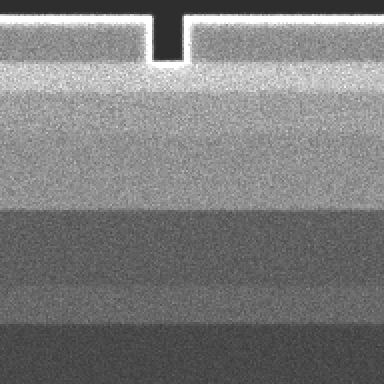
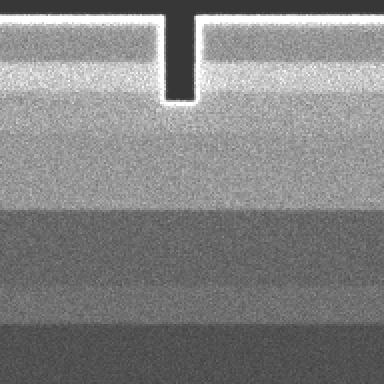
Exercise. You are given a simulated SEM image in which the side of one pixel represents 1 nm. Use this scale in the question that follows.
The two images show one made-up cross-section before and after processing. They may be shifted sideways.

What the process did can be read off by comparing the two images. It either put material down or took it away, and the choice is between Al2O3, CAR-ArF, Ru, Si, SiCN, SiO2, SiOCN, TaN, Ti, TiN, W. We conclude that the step removed Ru and W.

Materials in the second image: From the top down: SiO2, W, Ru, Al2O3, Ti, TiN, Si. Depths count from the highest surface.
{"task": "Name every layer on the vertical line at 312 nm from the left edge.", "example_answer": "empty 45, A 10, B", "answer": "SiO2 46, W 30, Ru 42, Al2O3 76, Ti 76, TiN 38, Si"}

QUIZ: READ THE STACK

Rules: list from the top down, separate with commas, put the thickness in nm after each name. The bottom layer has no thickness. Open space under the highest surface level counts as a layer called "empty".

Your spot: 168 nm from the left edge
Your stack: empty 86, Ru 32, Al2O3 76, Ti 76, TiN 38, Si